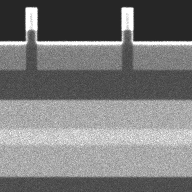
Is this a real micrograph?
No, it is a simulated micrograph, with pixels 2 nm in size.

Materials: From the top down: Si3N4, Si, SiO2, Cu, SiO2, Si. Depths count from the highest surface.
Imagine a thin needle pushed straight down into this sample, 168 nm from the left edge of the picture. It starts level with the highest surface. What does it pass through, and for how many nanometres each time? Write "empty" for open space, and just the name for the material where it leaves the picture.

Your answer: empty 68, Si3N4 56, Si 60, SiO2 58, Cu 32, SiO2 64, Si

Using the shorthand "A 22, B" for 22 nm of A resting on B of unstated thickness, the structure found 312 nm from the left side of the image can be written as empty 68, Si3N4 56, Si 60, SiO2 58, Cu 32, SiO2 64, Si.